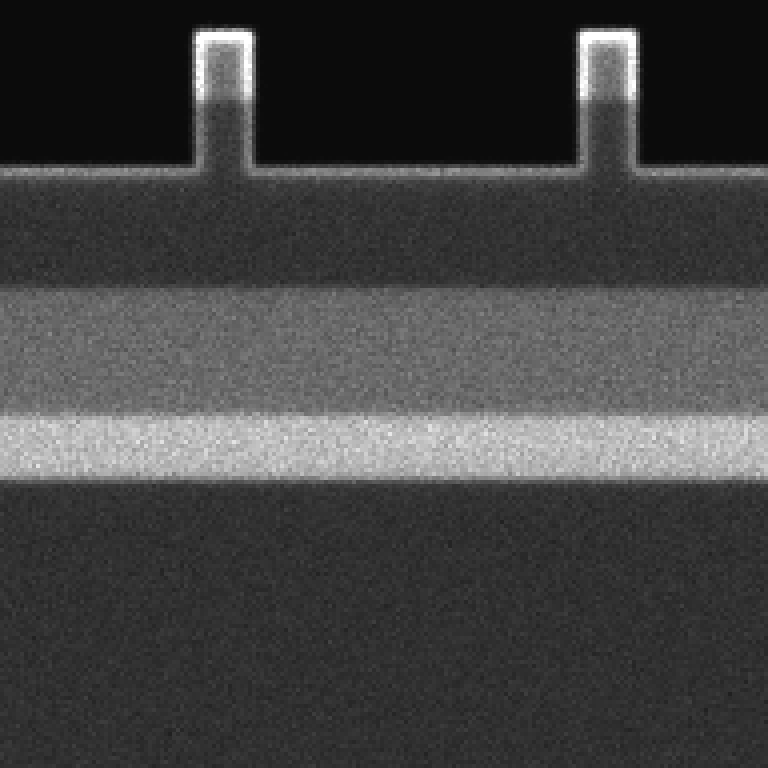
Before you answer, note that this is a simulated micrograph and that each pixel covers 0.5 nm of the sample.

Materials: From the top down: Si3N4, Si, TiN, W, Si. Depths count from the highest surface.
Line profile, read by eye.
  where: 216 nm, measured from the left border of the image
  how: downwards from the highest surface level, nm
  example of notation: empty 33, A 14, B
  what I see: empty 68, Si 60, TiN 64, W 32, Si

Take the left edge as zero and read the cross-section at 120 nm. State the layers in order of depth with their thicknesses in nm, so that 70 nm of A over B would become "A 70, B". Si3N4 34, Si 94, TiN 64, W 32, Si